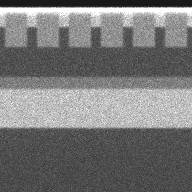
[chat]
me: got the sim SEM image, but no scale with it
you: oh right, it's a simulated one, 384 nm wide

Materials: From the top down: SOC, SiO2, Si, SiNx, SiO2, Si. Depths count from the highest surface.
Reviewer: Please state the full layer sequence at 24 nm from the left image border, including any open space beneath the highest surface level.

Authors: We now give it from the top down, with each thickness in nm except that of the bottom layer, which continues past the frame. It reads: SOC 78, Si 60, SiNx 24, SiO2 78, Si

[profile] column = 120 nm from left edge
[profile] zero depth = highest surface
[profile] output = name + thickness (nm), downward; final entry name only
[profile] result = SOC 10, SiO2 28, Si 100, SiNx 24, SiO2 78, Si